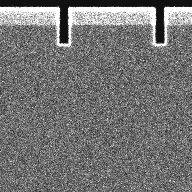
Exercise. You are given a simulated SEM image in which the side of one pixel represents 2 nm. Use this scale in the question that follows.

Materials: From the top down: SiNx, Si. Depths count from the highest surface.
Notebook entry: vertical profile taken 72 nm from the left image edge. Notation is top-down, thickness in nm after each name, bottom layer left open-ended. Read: SiNx 34, Si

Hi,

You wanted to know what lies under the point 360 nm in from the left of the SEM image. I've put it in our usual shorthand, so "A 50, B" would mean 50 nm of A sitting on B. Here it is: SiNx 34, Si